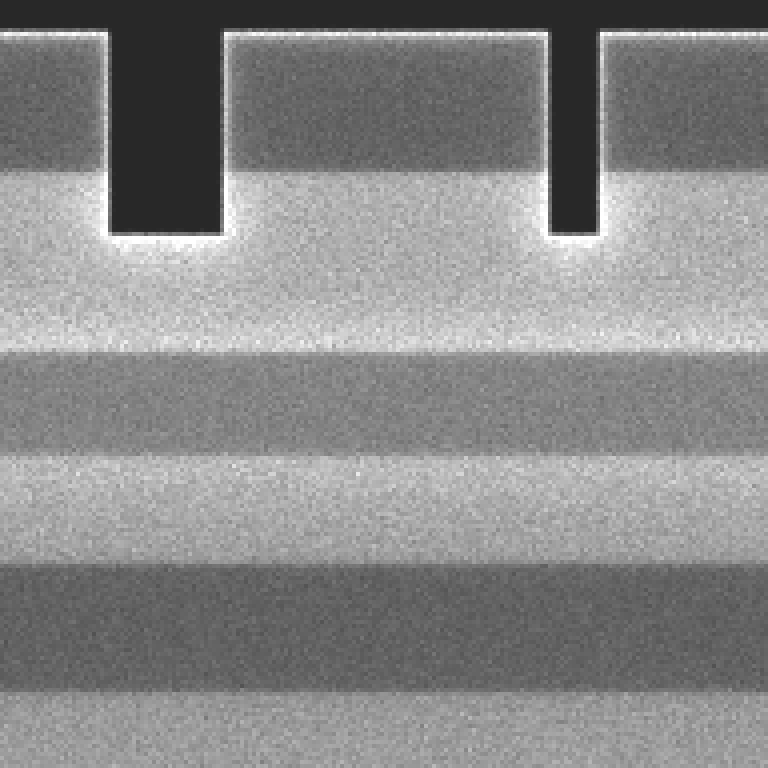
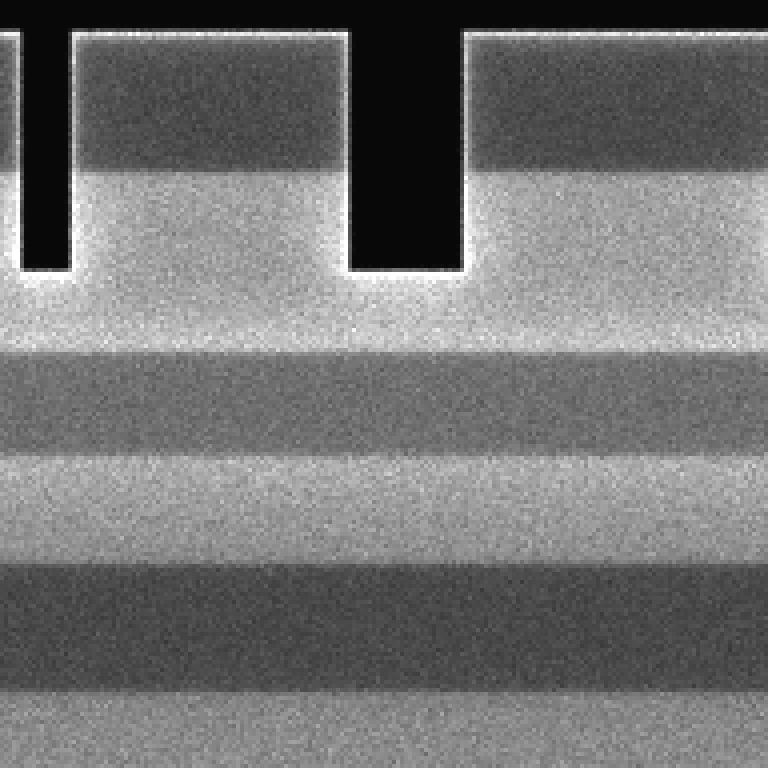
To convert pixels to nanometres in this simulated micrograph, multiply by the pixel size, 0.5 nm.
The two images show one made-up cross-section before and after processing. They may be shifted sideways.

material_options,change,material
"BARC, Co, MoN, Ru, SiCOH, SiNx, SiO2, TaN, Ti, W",removed,W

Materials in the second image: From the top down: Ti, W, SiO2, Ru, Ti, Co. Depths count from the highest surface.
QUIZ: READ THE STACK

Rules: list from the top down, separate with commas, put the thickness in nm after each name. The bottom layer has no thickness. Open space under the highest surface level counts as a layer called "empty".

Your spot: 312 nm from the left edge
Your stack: Ti 70, W 90, SiO2 52, Ru 54, Ti 64, Co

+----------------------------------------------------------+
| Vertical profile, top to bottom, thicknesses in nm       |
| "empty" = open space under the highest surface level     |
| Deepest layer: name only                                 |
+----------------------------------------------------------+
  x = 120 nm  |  Ti 70, W 90, SiO2 52, Ru 54, Ti 64, Co